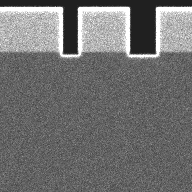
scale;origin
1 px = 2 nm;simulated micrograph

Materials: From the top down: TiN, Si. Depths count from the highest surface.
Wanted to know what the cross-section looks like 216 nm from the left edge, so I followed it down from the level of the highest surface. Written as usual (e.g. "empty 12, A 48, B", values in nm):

TiN 88, Si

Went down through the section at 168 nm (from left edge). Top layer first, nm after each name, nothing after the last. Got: TiN 88, Si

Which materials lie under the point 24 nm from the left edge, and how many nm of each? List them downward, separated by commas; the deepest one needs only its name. TiN 88, Si